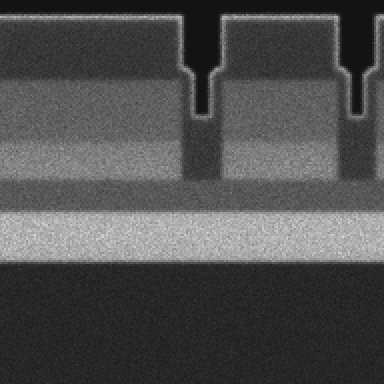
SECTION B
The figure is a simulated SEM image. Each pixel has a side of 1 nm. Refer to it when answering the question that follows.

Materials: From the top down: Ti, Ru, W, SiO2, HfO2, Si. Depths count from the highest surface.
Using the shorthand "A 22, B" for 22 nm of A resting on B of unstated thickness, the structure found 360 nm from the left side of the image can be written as empty 100, Ti 64, SiO2 32, HfO2 50, Si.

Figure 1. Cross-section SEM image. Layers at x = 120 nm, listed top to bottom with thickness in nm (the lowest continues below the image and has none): Ti 64, Ru 62, W 38, SiO2 32, HfO2 50, Si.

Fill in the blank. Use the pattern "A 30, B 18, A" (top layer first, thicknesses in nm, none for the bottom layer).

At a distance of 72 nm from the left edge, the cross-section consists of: Ti 64, Ru 62, W 38, SiO2 32, HfO2 50, Si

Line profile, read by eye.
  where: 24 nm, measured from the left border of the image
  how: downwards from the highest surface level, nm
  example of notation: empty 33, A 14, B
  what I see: Ti 64, Ru 62, W 38, SiO2 32, HfO2 50, Si